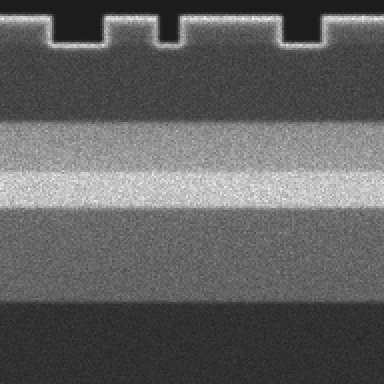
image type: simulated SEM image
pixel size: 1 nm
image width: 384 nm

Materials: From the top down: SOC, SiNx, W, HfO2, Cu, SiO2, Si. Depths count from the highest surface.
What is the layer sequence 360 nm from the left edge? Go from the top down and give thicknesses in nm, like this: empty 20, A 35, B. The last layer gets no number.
SOC 28, SiNx 78, W 50, HfO2 36, Cu 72, SiO2 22, Si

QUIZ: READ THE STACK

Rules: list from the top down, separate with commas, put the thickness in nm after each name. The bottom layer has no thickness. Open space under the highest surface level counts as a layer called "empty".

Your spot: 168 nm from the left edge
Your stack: empty 28, SiNx 78, W 50, HfO2 36, Cu 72, SiO2 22, Si